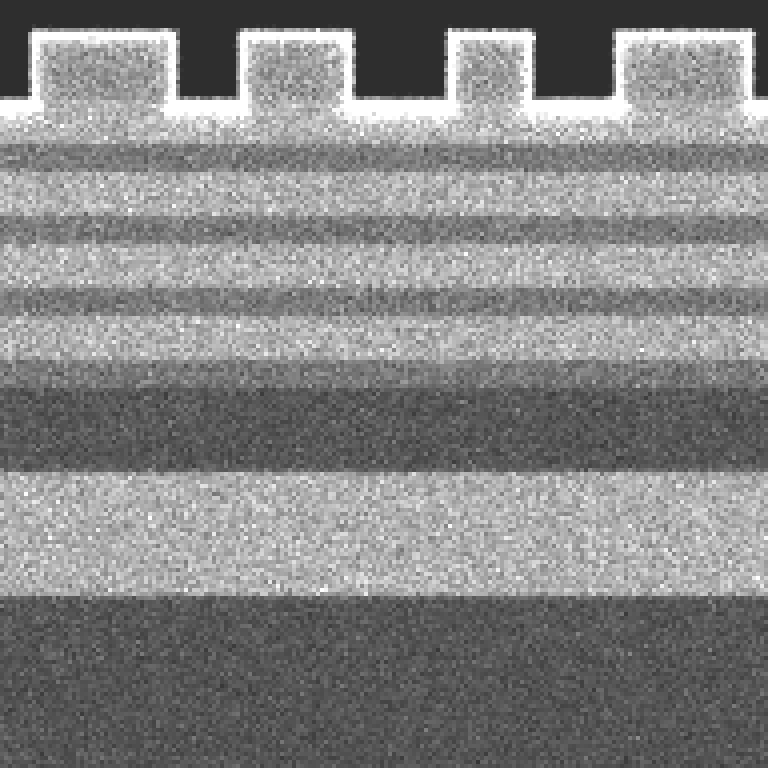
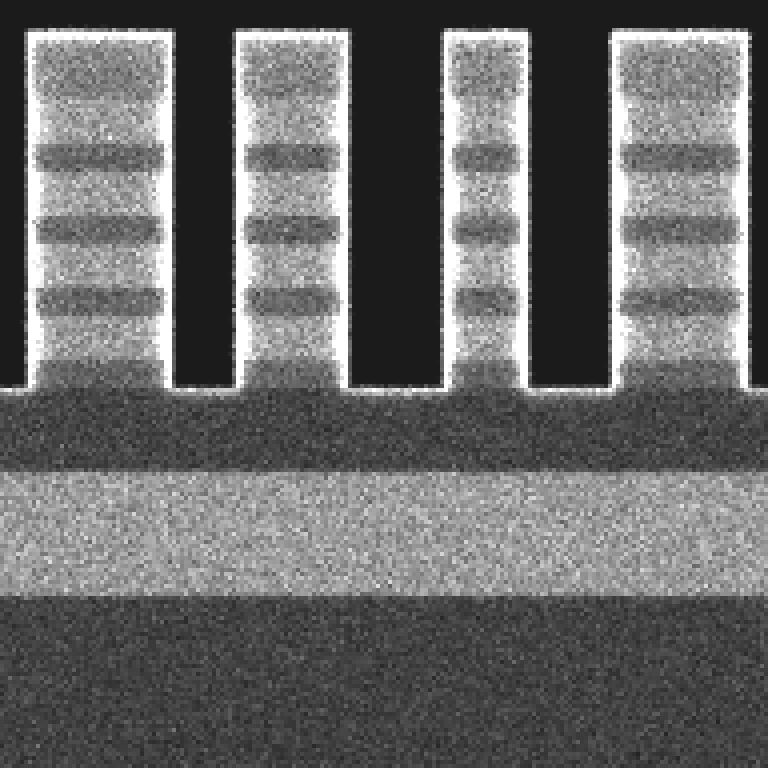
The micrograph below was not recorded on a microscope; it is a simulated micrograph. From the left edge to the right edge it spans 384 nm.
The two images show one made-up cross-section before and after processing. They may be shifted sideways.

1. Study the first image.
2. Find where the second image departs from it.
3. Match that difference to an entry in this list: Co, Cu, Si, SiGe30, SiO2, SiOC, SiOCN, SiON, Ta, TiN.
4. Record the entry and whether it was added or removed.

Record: SiO2 and SiOCN / removed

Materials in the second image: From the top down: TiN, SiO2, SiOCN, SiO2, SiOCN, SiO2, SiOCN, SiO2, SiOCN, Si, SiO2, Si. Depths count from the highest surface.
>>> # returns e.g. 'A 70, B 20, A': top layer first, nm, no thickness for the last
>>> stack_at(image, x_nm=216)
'empty 178, Si 42, SiO2 62, Si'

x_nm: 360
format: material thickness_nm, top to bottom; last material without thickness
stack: TiN 34, SiO2 22, SiOCN 14, SiO2 22, SiOCN 14, SiO2 22, SiOCN 14, SiO2 22, SiOCN 14, Si 42, SiO2 62, Si